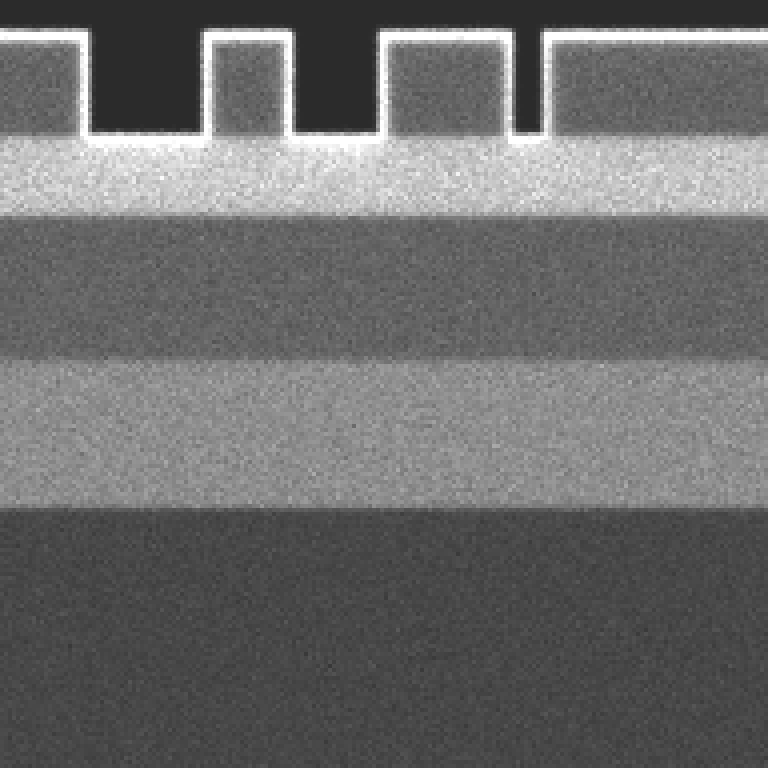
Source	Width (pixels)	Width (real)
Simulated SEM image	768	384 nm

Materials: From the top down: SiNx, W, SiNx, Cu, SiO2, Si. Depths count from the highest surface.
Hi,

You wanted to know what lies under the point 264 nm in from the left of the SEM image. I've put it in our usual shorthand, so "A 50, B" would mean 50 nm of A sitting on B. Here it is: empty 52, W 40, SiNx 72, Cu 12, SiO2 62, Si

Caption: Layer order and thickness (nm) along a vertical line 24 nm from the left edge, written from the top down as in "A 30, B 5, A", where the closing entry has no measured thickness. SiNx 52, W 40, SiNx 72, Cu 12, SiO2 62, Si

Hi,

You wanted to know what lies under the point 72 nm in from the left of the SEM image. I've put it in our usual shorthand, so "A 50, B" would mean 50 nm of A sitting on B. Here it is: empty 52, W 40, SiNx 72, Cu 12, SiO2 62, Si